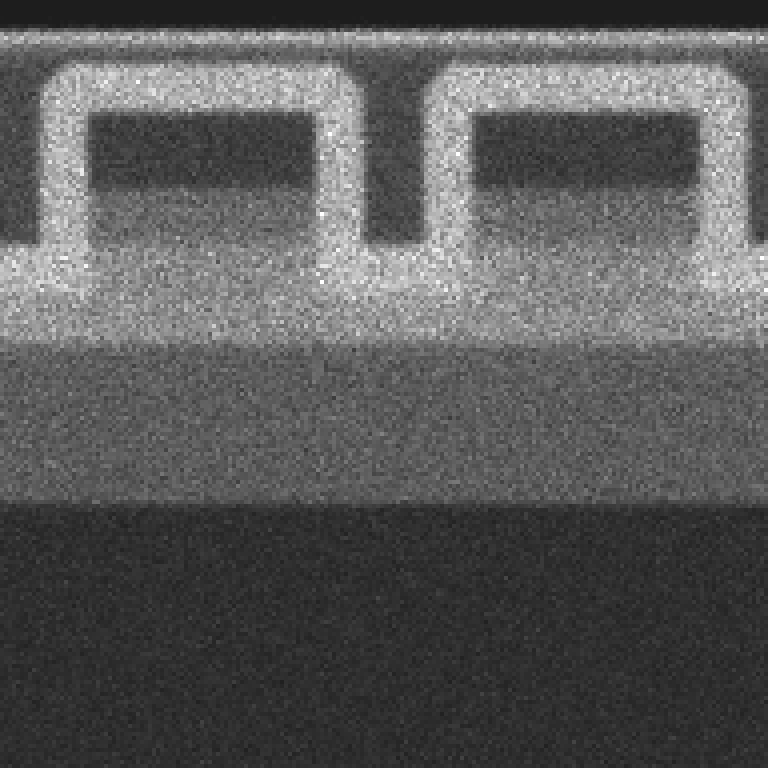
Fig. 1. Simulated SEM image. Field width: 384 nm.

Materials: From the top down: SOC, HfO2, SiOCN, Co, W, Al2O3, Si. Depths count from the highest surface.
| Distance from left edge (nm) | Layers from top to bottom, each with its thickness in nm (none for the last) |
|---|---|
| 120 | SOC 16, HfO2 24, SiOCN 38, Co 28, W 50, Al2O3 80, Si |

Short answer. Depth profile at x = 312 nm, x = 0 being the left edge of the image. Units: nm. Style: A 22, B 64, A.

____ SOC 16, HfO2 24, SiOCN 38, Co 28, W 50, Al2O3 80, Si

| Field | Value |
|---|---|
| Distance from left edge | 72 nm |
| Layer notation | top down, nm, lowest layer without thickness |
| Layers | SOC 16, HfO2 24, SiOCN 38, Co 28, W 50, Al2O3 80, Si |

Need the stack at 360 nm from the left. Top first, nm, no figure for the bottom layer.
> SOC 16, HfO2 114, W 26, Al2O3 80, Si